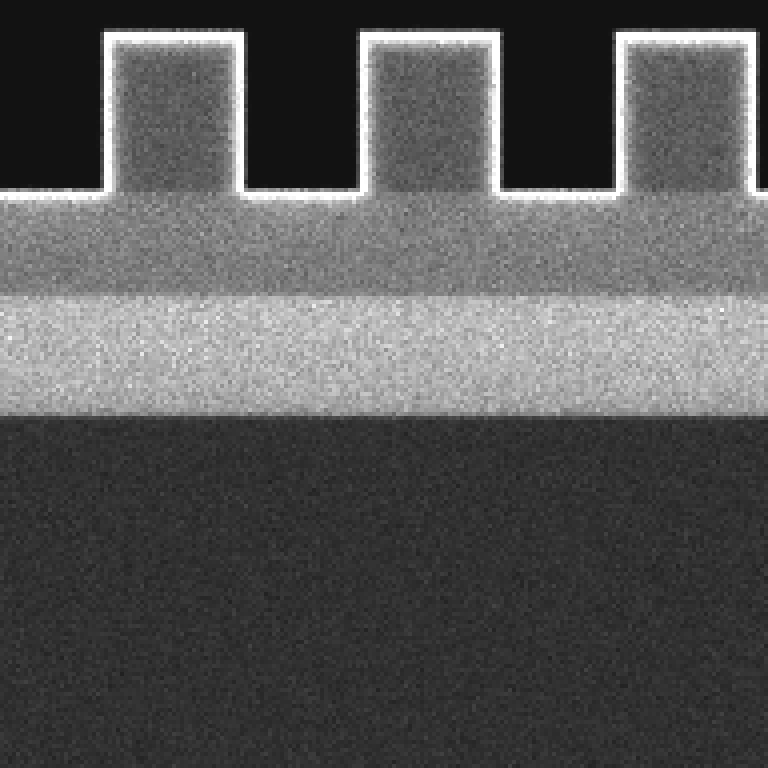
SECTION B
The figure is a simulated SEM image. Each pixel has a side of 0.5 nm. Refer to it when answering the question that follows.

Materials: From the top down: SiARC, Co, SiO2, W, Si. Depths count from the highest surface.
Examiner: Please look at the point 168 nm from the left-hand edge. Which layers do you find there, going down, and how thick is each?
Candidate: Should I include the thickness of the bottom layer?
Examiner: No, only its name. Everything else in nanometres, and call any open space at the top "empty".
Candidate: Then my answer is empty 80, Co 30, SiO2 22, W 60, Si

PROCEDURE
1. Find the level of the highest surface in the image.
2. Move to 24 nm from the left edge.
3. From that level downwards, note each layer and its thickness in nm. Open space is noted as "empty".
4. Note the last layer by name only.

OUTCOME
empty 80, Co 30, SiO2 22, W 60, Si